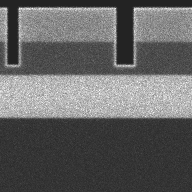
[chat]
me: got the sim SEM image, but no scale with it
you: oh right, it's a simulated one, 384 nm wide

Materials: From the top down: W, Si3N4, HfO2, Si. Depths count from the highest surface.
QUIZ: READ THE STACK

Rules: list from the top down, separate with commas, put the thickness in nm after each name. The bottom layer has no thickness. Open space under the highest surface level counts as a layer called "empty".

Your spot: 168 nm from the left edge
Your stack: W 68, Si3N4 66, HfO2 86, Si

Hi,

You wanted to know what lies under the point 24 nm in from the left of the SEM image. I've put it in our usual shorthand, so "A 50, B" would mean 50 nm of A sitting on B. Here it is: empty 114, Si3N4 20, HfO2 86, Si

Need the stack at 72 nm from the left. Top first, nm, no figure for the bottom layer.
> W 68, Si3N4 66, HfO2 86, Si